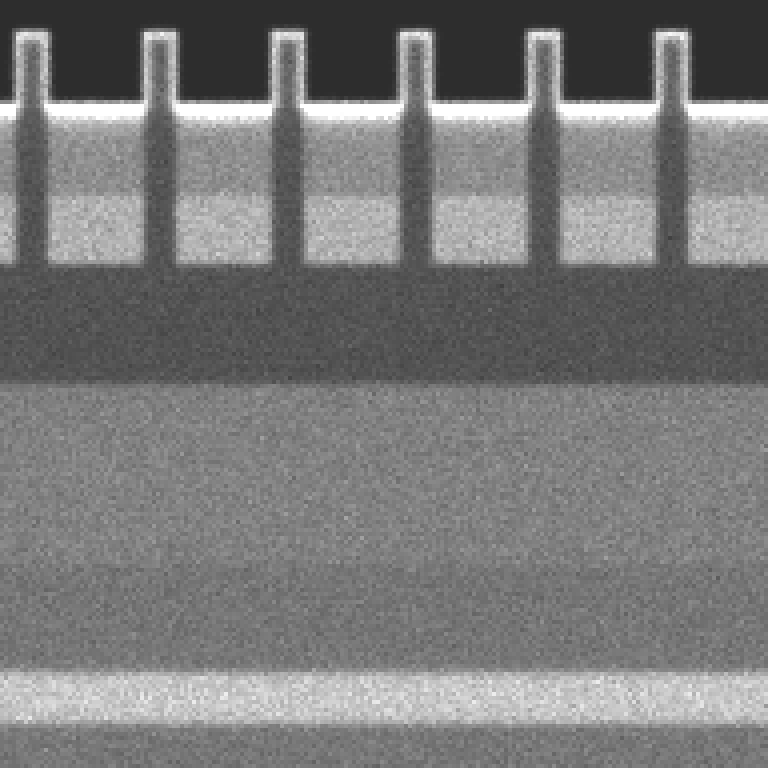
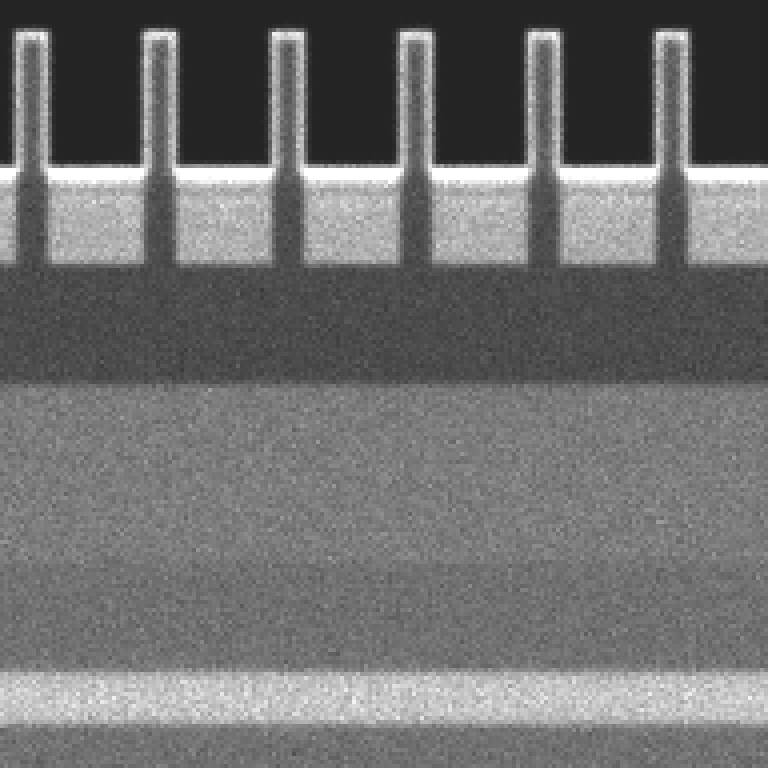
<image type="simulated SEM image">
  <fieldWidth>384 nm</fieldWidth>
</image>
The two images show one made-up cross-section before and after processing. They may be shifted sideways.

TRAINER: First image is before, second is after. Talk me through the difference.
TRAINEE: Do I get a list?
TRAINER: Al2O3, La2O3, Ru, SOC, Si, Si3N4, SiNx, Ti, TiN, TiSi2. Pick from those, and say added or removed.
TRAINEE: removed: SOC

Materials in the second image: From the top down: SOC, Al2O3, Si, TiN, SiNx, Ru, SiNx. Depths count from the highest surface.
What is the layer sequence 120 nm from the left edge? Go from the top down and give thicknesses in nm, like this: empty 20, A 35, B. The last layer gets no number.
empty 68, SOC 14, Al2O3 34, Si 60, TiN 90, SiNx 54, Ru 26, SiNx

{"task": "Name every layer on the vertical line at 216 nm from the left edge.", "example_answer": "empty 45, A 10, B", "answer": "empty 68, SOC 14, Al2O3 34, Si 60, TiN 90, SiNx 54, Ru 26, SiNx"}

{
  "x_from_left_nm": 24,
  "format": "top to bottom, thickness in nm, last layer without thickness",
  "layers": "empty 68, SOC 14, Al2O3 34, Si 60, TiN 90, SiNx 54, Ru 26, SiNx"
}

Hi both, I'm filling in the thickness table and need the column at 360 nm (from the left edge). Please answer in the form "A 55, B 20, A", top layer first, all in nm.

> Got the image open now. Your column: empty 68, SOC 14, Al2O3 34, Si 60, TiN 90, SiNx 54, Ru 26, SiNx